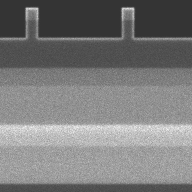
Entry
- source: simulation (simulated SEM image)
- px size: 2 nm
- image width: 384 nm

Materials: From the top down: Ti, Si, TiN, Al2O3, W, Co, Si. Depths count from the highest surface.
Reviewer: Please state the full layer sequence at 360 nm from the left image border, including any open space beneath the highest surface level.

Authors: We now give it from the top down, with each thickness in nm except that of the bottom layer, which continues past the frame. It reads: empty 60, Si 60, TiN 36, Al2O3 78, W 42, Co 76, Si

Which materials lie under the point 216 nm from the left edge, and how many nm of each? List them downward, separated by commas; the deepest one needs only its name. empty 60, Si 60, TiN 36, Al2O3 78, W 42, Co 76, Si